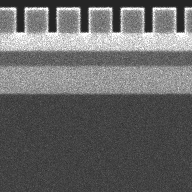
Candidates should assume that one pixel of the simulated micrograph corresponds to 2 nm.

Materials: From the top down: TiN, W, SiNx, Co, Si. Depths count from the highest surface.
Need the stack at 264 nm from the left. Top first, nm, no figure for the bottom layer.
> TiN 50, W 36, SiNx 30, Co 56, Si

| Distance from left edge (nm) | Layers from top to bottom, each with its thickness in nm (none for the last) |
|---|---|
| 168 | empty 50, W 36, SiNx 30, Co 56, Si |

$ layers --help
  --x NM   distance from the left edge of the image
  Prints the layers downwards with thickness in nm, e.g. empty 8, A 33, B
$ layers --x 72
TiN 50, W 36, SiNx 30, Co 56, Si